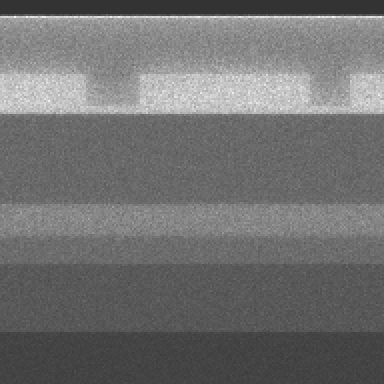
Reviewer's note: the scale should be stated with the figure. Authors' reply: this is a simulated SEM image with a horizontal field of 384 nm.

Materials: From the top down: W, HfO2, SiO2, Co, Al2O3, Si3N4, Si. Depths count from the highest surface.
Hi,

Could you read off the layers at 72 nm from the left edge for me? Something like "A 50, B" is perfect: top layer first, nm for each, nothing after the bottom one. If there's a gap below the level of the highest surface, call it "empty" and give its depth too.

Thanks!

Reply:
W 58, HfO2 40, SiO2 90, Co 32, Al2O3 28, Si3N4 68, Si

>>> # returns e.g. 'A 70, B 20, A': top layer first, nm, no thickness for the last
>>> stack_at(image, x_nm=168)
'W 58, HfO2 40, SiO2 90, Co 32, Al2O3 28, Si3N4 68, Si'